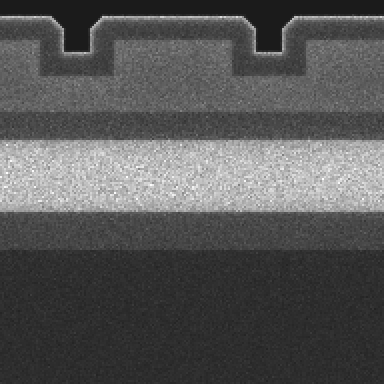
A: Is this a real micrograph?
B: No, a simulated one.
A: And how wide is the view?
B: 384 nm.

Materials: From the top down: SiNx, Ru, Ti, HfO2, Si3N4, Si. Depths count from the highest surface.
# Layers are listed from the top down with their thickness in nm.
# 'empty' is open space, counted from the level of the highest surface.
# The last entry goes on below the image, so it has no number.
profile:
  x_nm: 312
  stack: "SiNx 24, Ru 72, Ti 28, HfO2 72, Si3N4 38, Si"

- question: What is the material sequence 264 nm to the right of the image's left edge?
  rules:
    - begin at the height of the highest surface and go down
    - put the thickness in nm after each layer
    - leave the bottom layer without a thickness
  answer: empty 36, SiNx 24, Ru 36, Ti 28, HfO2 72, Si3N4 38, Si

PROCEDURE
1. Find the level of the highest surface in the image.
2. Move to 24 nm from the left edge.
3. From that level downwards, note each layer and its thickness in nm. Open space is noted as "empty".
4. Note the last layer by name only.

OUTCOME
SiNx 24, Ru 72, Ti 28, HfO2 72, Si3N4 38, Si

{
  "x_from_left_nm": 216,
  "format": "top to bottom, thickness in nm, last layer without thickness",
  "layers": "SiNx 24, Ru 72, Ti 28, HfO2 72, Si3N4 38, Si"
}